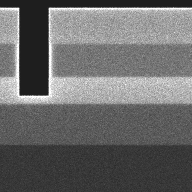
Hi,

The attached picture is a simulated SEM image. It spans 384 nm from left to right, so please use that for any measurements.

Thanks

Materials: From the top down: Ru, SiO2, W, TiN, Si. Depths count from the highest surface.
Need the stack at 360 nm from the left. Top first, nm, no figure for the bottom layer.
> Ru 72, SiO2 66, W 54, TiN 82, Si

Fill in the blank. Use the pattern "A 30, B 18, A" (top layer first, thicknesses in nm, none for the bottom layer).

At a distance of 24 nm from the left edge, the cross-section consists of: Ru 72, SiO2 66, W 54, TiN 82, Si